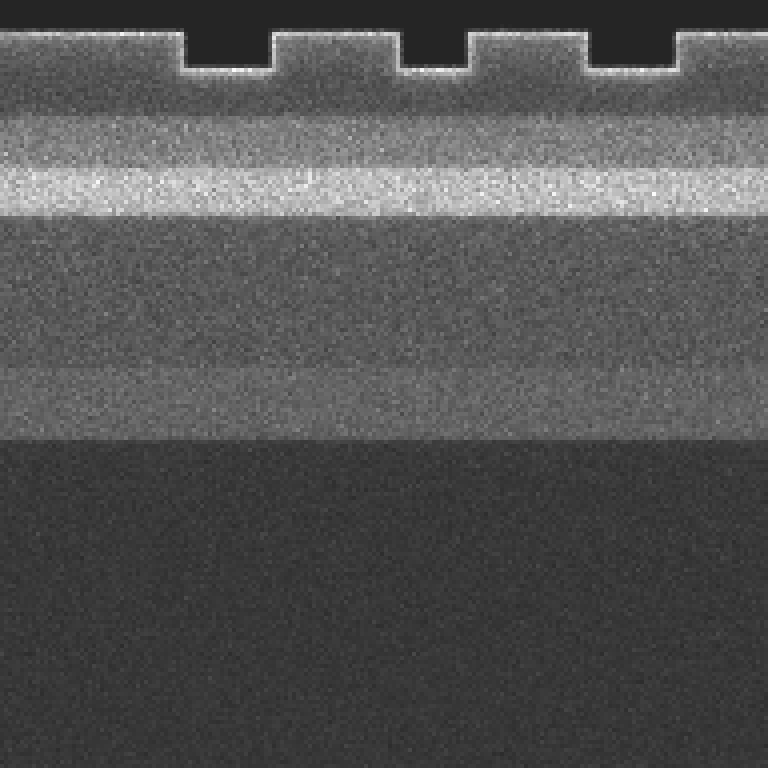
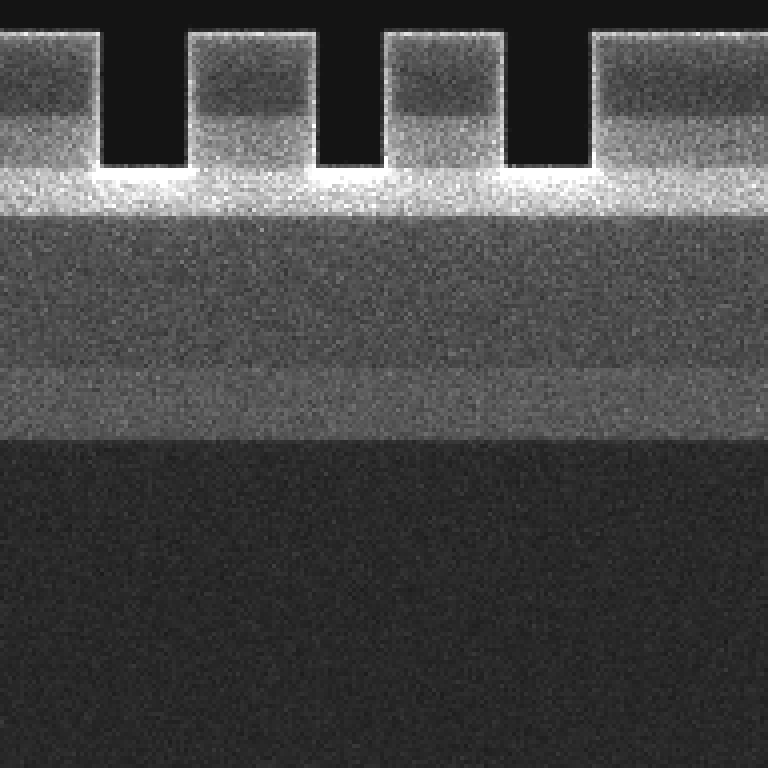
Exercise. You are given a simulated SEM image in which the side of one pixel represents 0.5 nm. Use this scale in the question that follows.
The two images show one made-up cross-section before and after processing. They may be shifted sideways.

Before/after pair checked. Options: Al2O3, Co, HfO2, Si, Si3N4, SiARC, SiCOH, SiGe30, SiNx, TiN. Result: removed Co and Si3N4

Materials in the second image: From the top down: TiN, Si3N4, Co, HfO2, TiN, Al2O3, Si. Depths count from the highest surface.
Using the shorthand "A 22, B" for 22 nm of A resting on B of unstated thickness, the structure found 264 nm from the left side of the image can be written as empty 68, HfO2 24, TiN 76, Al2O3 36, Si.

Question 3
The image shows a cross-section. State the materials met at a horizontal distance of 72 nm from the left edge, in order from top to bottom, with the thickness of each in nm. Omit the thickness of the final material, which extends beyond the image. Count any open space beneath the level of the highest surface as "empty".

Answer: empty 68, HfO2 24, TiN 76, Al2O3 36, Si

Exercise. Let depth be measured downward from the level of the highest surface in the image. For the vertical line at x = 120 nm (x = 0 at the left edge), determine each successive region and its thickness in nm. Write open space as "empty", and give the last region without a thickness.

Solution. TiN 18, Si3N4 24, Co 26, HfO2 24, TiN 76, Al2O3 36, Si